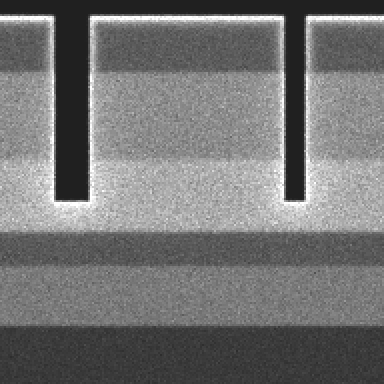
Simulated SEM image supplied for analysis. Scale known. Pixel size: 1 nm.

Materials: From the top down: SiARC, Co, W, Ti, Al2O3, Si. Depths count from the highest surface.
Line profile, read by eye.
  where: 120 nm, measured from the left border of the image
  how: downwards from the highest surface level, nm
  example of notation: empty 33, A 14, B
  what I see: SiARC 56, Co 88, W 72, Ti 34, Al2O3 60, Si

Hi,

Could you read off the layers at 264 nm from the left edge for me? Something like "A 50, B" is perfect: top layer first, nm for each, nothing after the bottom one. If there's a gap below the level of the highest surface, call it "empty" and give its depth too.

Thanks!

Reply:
SiARC 56, Co 88, W 72, Ti 34, Al2O3 60, Si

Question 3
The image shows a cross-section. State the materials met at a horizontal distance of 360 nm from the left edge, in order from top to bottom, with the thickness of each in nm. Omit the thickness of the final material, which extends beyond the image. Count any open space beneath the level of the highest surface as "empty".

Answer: SiARC 56, Co 88, W 72, Ti 34, Al2O3 60, Si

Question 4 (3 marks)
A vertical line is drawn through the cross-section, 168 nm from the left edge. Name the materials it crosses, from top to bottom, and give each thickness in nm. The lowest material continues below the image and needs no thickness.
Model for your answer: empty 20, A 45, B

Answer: SiARC 56, Co 88, W 72, Ti 34, Al2O3 60, Si